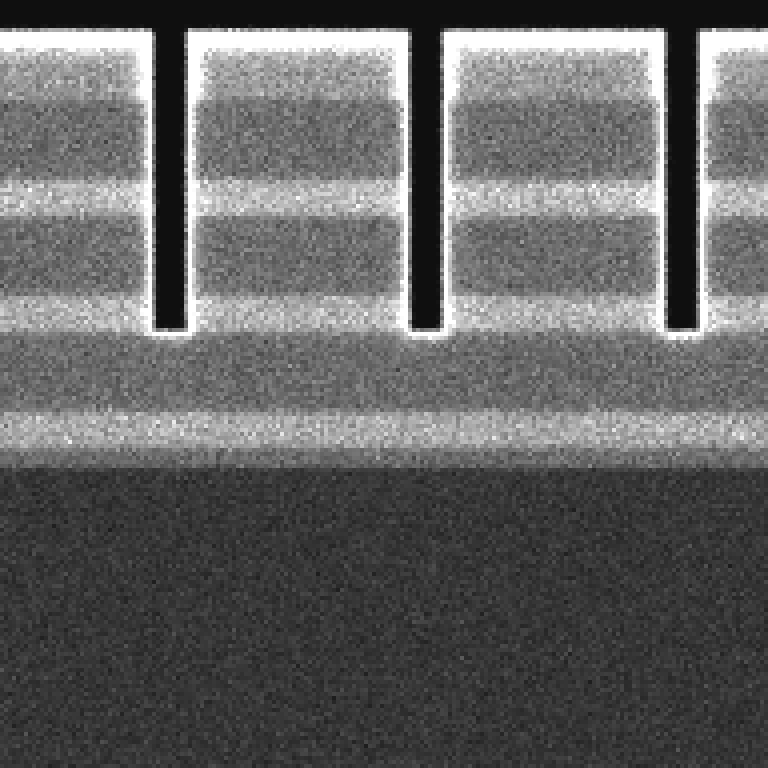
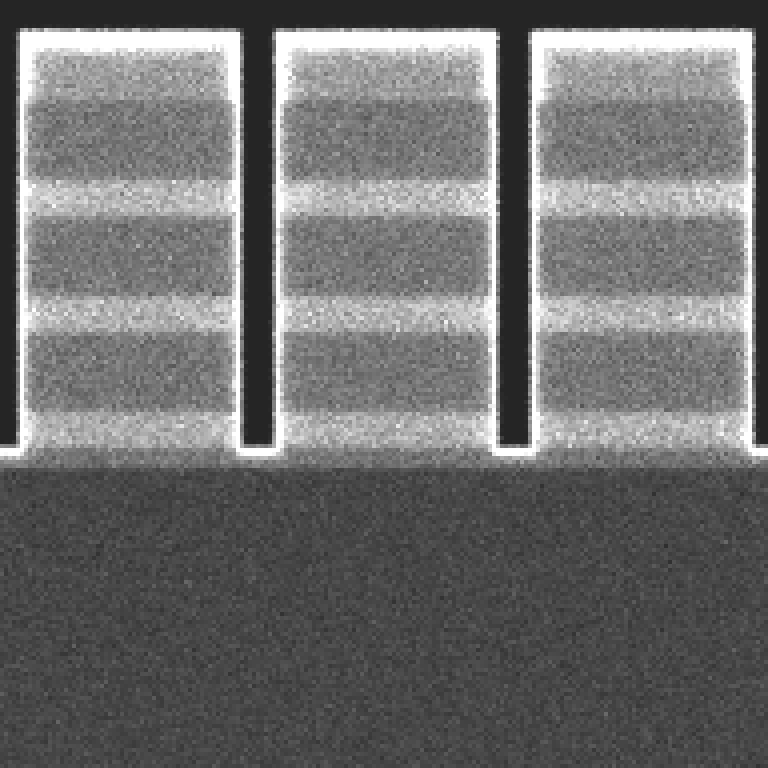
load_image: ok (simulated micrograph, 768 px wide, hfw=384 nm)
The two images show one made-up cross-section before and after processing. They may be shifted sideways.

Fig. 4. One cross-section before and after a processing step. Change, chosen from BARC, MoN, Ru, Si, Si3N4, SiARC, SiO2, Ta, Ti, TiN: Ru and TiN removed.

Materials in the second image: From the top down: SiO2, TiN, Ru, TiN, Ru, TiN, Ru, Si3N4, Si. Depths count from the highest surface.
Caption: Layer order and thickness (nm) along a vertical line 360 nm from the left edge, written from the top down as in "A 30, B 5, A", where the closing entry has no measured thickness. SiO2 34, TiN 40, Ru 18, TiN 40, Ru 18, TiN 40, Ru 18, Si3N4 10, Si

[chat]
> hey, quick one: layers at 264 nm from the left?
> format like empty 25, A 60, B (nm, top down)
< empty 208, Si3N4 10, Si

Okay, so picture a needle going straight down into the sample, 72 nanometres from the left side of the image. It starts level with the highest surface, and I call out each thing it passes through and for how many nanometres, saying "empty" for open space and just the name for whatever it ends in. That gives SiO2 34, TiN 40, Ru 18, TiN 40, Ru 18, TiN 40, Ru 18, Si3N4 10, Si